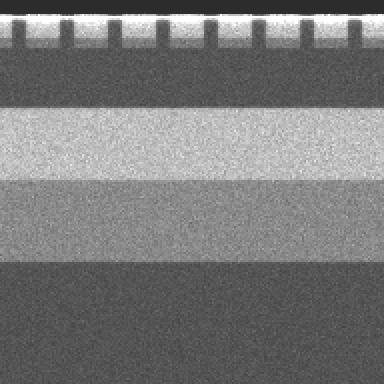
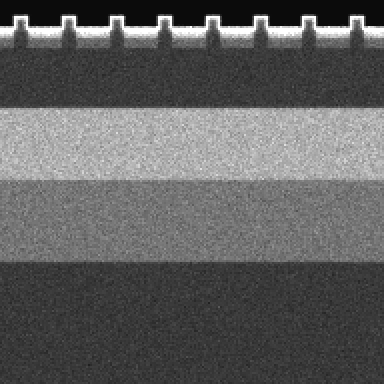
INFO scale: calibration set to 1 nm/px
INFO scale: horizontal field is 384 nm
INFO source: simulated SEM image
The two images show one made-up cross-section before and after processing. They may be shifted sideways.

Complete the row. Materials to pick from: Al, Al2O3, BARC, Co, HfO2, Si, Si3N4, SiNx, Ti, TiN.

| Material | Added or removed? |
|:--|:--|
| Co | removed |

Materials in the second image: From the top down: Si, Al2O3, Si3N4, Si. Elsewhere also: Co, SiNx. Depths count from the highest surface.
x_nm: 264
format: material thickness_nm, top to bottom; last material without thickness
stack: Si 92, Al2O3 72, Si3N4 82, Si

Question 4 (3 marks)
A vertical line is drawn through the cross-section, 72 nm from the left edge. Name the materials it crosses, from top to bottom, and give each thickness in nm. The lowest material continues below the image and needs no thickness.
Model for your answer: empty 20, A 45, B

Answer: Si 92, Al2O3 72, Si3N4 82, Si